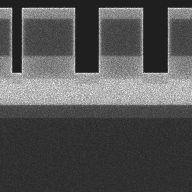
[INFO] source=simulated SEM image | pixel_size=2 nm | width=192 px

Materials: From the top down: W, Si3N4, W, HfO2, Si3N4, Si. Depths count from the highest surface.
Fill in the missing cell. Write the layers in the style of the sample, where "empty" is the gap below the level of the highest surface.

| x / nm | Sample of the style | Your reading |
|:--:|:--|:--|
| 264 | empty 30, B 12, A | W 22, Si3N4 74, W 46, HfO2 52, Si3N4 26, Si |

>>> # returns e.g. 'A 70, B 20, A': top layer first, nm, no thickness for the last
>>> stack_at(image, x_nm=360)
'W 22, Si3N4 74, W 46, HfO2 52, Si3N4 26, Si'